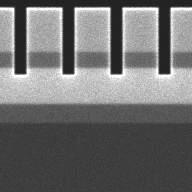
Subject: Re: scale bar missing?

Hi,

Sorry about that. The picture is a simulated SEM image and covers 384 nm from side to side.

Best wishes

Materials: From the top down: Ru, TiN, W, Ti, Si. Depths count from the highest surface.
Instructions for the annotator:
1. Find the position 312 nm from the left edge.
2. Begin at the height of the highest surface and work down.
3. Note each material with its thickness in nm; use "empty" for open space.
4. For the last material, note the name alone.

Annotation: Ru 88, TiN 32, W 72, Ti 38, Si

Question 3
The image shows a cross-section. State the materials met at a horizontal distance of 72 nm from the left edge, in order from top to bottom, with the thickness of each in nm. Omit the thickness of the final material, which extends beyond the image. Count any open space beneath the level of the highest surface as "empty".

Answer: Ru 88, TiN 32, W 72, Ti 38, Si